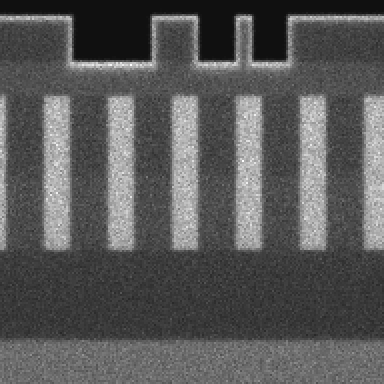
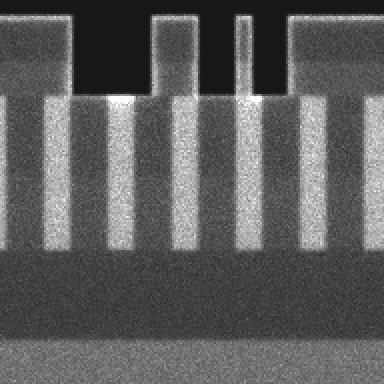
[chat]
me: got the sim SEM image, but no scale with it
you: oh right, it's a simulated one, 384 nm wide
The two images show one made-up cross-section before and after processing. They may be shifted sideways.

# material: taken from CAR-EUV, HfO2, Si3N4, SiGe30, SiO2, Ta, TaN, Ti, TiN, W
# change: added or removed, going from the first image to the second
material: SiO2
change: removed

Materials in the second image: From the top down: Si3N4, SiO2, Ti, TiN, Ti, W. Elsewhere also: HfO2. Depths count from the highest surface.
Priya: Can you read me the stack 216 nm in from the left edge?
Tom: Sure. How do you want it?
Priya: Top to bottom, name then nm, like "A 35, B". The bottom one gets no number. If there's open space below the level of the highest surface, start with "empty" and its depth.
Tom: empty 80, Ti 80, TiN 74, Ti 90, W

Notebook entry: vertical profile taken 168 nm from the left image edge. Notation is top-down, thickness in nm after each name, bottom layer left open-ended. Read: Si3N4 46, SiO2 34, Ti 80, TiN 74, Ti 90, W